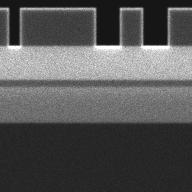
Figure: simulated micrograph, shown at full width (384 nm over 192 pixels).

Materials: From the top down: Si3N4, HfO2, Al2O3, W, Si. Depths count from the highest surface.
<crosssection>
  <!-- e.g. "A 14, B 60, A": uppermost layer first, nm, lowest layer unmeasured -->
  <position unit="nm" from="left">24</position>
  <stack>empty 76, HfO2 68, Al2O3 14, W 72, Si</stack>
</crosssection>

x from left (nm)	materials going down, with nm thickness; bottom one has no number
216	empty 76, HfO2 68, Al2O3 14, W 72, Si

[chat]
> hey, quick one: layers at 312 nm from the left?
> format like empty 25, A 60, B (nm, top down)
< empty 76, HfO2 68, Al2O3 14, W 72, Si